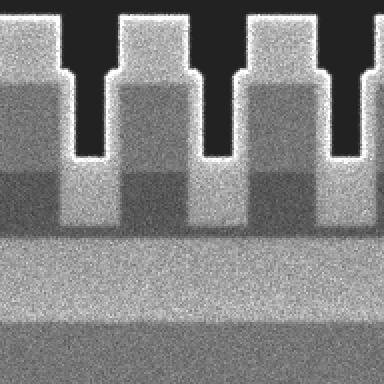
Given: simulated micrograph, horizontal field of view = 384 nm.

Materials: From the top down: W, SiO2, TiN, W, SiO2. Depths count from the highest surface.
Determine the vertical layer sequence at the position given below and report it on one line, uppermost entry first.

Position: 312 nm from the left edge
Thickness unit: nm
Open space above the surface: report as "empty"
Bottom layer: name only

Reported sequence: W 68, SiO2 88, TiN 66, W 84, SiO2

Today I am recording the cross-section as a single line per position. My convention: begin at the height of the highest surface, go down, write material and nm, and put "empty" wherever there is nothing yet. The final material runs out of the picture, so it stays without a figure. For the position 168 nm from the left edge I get W 68, SiO2 88, TiN 66, W 84, SiO2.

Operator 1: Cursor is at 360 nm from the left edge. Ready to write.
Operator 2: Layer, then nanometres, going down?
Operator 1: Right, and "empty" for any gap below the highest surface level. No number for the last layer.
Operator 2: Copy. empty 142, W 68, TiN 12, W 84, SiO2